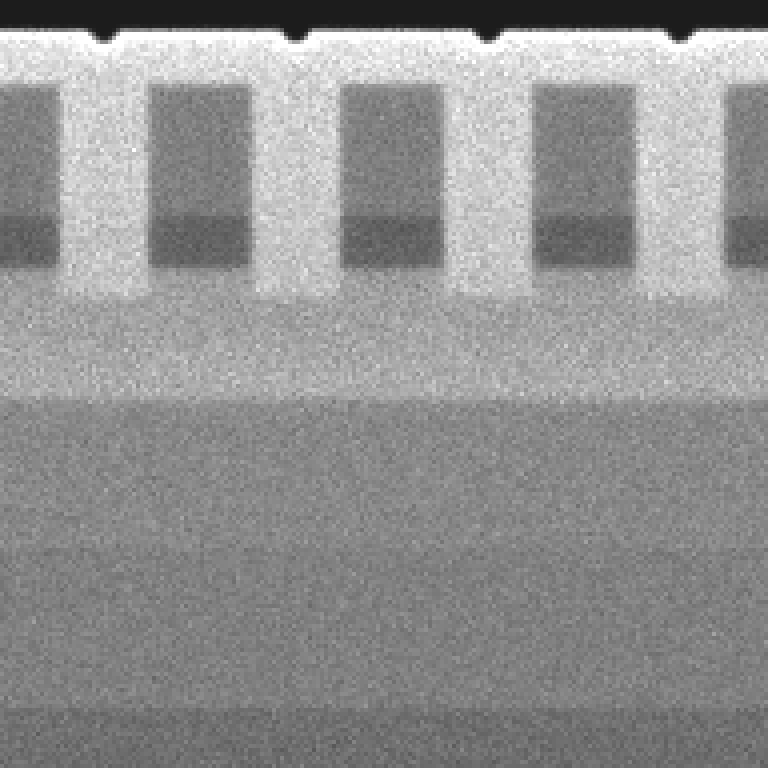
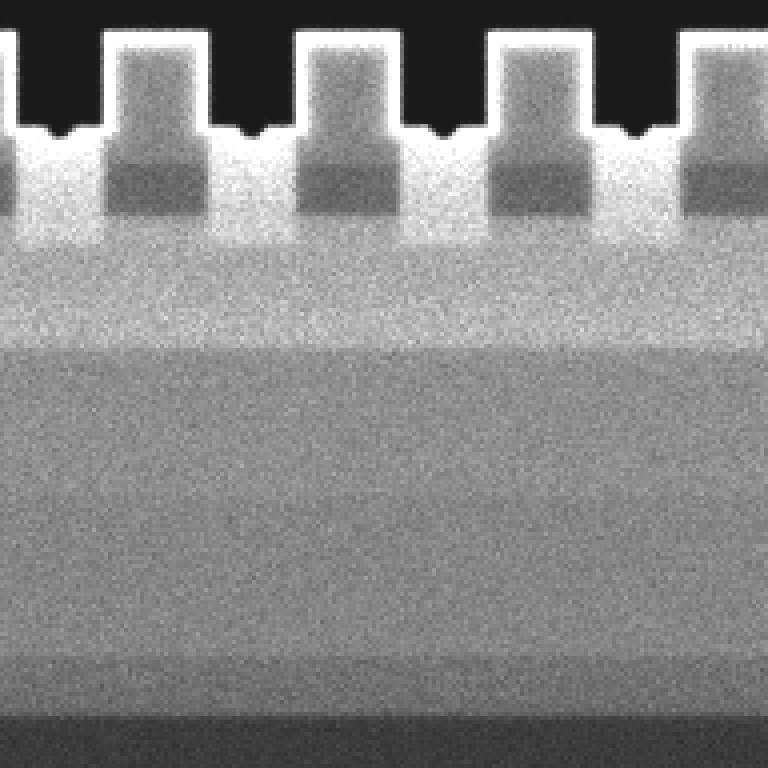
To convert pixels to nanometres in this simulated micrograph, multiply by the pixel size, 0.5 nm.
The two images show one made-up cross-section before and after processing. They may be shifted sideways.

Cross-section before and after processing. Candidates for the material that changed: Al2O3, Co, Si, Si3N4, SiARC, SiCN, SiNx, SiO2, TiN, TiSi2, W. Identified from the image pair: W (removed).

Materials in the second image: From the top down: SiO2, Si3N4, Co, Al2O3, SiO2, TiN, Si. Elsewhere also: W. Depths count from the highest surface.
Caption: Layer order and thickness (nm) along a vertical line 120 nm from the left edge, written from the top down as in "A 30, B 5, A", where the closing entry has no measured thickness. empty 52, W 54, Co 52, Al2O3 74, SiO2 80, TiN 30, Si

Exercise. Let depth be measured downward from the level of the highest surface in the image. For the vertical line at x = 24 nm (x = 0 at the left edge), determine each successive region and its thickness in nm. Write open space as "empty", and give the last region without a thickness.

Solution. empty 52, W 54, Co 52, Al2O3 74, SiO2 80, TiN 30, Si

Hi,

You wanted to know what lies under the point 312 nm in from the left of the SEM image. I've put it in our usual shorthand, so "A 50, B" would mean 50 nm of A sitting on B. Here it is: empty 52, W 54, Co 52, Al2O3 74, SiO2 80, TiN 30, Si